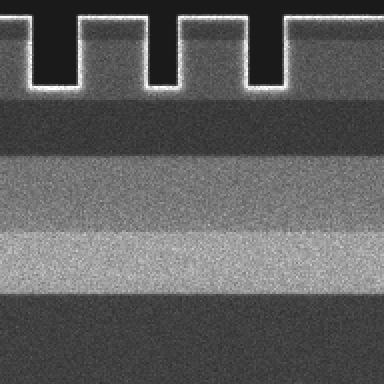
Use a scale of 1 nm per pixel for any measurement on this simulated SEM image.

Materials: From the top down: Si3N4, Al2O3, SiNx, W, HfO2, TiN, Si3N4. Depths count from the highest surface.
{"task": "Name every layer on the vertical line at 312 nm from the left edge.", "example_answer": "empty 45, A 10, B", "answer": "Si3N4 24, Al2O3 60, SiNx 56, W 76, HfO2 62, TiN 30, Si3N4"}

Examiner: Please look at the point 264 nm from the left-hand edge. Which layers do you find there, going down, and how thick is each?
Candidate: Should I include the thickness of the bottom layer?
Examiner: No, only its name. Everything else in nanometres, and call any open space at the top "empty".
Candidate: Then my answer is empty 70, Al2O3 14, SiNx 56, W 76, HfO2 62, TiN 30, Si3N4